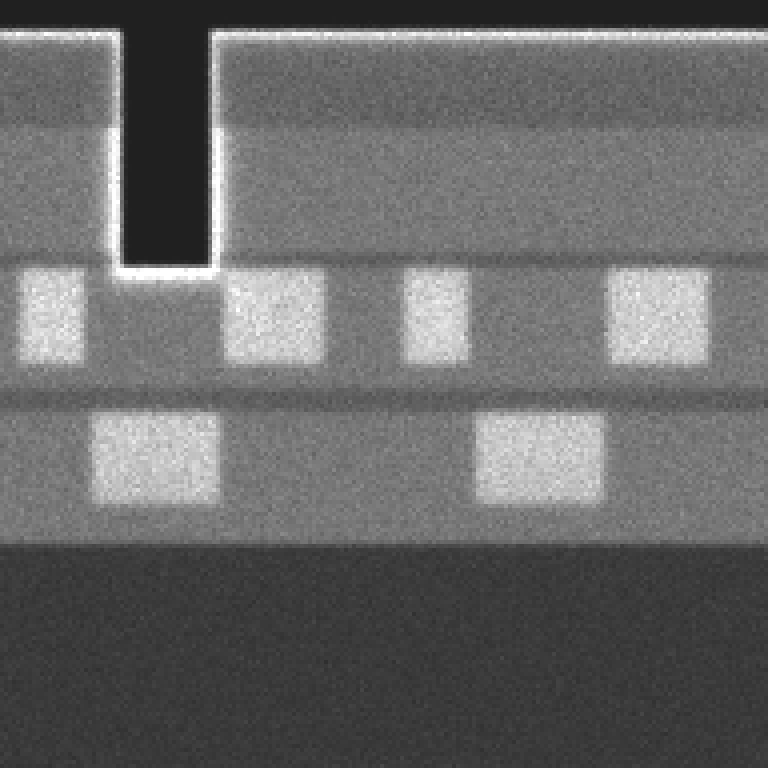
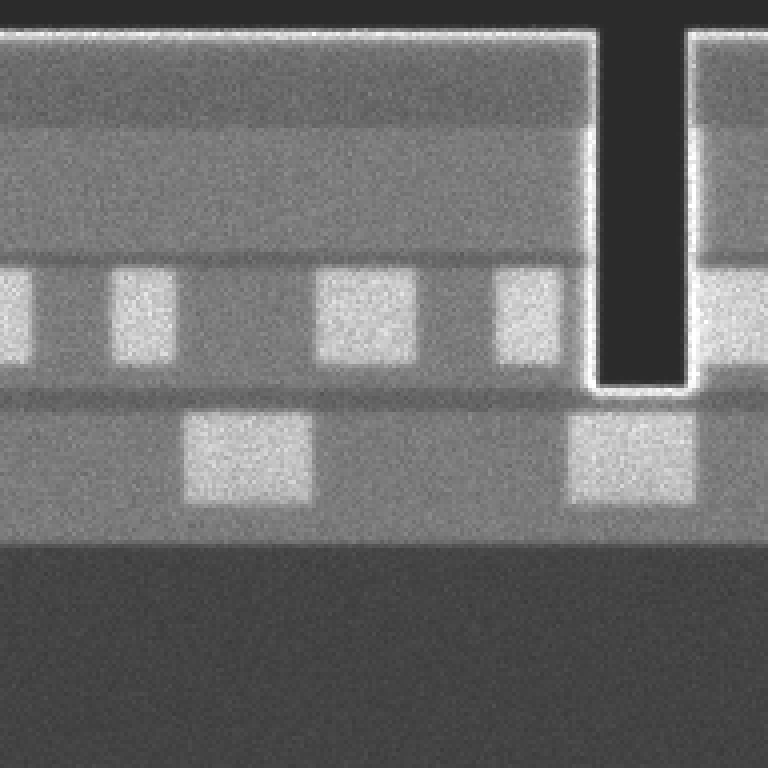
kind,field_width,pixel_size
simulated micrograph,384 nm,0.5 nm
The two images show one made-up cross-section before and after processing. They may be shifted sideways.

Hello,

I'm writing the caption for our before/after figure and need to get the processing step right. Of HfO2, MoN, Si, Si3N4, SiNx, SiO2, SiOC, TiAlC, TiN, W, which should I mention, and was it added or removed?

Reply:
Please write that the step removed SiO2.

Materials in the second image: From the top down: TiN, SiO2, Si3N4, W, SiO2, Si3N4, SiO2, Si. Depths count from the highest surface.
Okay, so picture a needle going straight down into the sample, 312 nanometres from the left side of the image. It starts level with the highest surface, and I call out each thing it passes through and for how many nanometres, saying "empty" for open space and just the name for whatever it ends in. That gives empty 178, Si3N4 12, W 46, SiO2 20, Si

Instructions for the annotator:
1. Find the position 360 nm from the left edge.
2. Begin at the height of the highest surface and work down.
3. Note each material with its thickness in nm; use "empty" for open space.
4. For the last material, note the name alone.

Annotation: TiN 48, SiO2 62, Si3N4 8, W 48, SiO2 12, Si3N4 12, SiO2 66, Si